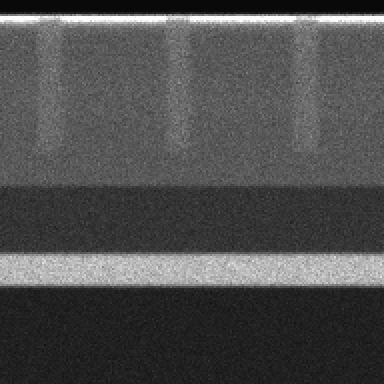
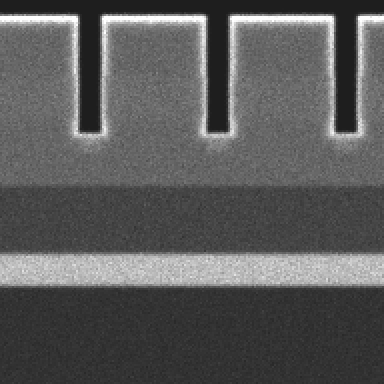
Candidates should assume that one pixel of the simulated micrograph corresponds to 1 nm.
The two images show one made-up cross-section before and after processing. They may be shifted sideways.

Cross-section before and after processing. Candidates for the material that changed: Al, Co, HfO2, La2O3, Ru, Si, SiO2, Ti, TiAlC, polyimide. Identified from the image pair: Ru (removed).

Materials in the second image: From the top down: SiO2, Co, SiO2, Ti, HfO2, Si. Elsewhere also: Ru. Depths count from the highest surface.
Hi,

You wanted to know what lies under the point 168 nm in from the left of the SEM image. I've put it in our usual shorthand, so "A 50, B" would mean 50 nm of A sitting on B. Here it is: SiO2 60, Co 44, SiO2 66, Ti 68, HfO2 32, Si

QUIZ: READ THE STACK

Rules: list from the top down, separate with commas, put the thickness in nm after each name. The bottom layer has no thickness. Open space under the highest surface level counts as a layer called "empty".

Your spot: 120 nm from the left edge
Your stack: SiO2 60, Co 44, SiO2 66, Ti 68, HfO2 32, Si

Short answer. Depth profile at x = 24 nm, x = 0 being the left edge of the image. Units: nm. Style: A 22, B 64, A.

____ SiO2 60, Co 44, SiO2 66, Ti 68, HfO2 32, Si